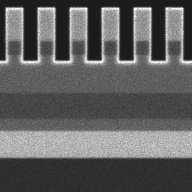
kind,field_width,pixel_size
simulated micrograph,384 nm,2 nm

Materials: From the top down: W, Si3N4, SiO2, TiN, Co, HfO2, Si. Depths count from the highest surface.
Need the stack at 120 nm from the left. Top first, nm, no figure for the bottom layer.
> empty 106, SiO2 64, TiN 52, Co 24, HfO2 54, Si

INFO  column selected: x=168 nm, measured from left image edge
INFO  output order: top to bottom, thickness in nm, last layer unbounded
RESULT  W 66, Si3N4 28, SiO2 76, TiN 52, Co 24, HfO2 54, Si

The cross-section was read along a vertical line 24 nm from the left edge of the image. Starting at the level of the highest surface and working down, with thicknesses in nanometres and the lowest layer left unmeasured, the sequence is W 66, Si3N4 28, SiO2 76, TiN 52, Co 24, HfO2 54, Si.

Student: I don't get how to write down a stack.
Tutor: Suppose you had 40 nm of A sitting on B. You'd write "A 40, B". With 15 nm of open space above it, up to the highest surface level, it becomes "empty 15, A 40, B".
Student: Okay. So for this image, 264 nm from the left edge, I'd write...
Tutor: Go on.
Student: empty 106, SiO2 64, TiN 52, Co 24, HfO2 54, Si